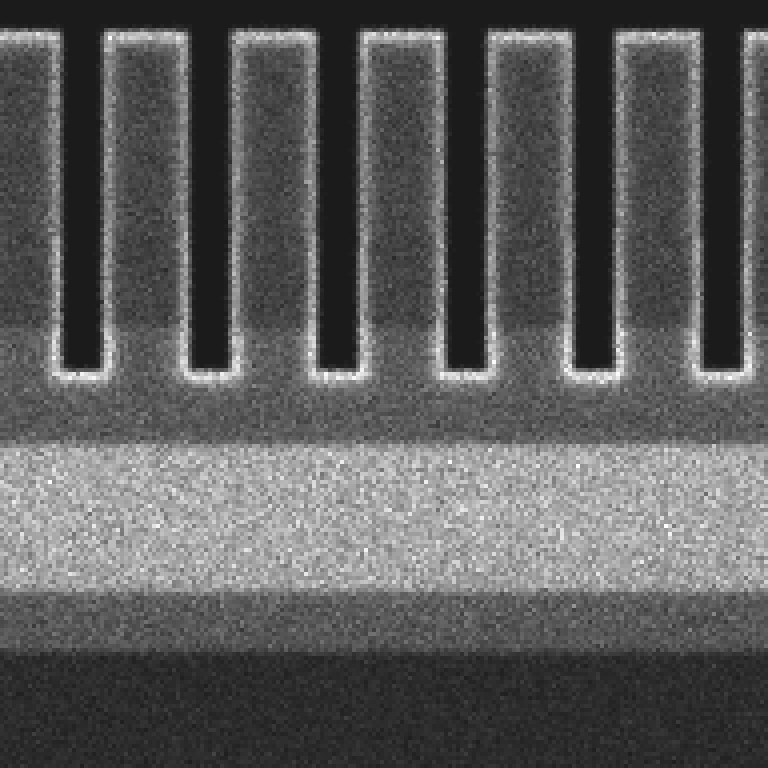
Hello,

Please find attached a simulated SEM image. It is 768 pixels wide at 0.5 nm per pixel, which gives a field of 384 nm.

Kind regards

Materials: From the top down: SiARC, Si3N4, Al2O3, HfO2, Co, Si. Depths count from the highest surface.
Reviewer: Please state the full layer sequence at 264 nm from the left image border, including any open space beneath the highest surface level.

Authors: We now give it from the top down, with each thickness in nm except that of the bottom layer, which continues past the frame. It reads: SiARC 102, Si3N4 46, Al2O3 58, HfO2 74, Co 30, Si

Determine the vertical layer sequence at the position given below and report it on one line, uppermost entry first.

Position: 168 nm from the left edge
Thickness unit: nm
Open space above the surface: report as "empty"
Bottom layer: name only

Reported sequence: empty 170, Al2O3 36, HfO2 74, Co 30, Si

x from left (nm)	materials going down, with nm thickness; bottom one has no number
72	SiARC 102, Si3N4 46, Al2O3 58, HfO2 74, Co 30, Si